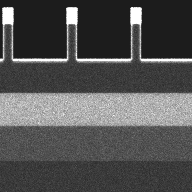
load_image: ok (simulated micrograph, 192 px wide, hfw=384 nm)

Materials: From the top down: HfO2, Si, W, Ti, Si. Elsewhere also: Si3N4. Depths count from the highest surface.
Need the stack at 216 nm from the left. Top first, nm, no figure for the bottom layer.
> empty 102, Si3N4 8, Si 60, W 66, Ti 70, Si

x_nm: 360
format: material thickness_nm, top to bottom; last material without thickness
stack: empty 102, Si3N4 8, Si 60, W 66, Ti 70, Si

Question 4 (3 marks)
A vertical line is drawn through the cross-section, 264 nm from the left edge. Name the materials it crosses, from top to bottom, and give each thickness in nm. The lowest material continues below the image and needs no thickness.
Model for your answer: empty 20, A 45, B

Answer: HfO2 32, Si 138, W 66, Ti 70, Si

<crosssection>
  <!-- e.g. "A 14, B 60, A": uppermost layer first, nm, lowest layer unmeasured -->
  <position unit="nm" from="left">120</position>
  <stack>empty 102, Si3N4 8, Si 60, W 66, Ti 70, Si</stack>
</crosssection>